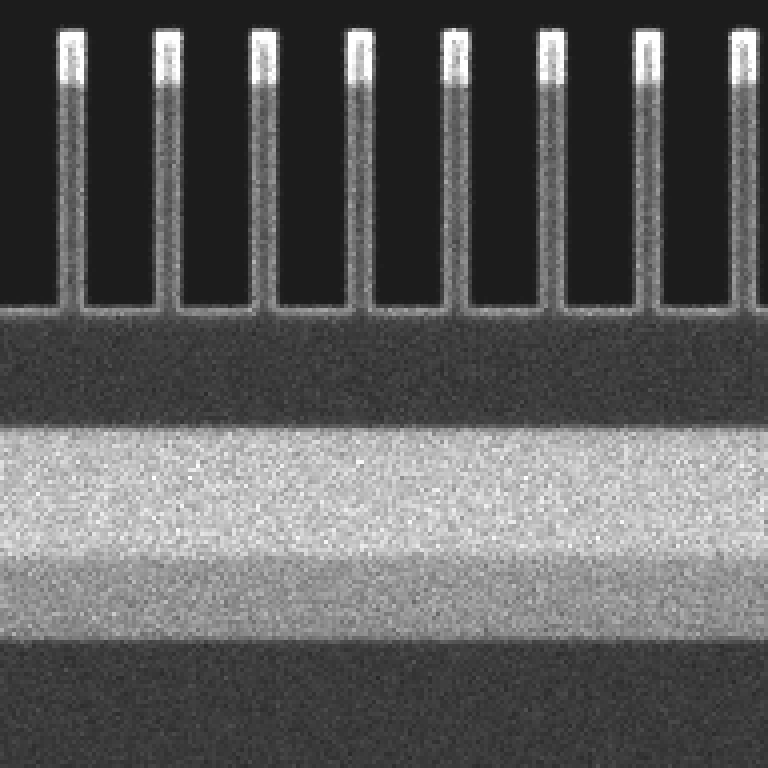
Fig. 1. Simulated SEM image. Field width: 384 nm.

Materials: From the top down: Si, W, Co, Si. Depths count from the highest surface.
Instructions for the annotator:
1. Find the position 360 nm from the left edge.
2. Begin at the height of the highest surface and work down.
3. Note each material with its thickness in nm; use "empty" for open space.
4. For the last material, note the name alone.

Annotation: empty 138, Si 60, W 64, Co 42, Si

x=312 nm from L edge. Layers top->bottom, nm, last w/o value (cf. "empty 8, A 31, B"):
empty 138, Si 60, W 64, Co 42, Si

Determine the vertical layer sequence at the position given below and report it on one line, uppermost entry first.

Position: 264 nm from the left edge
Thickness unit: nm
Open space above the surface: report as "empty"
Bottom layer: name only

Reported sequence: empty 138, Si 60, W 64, Co 42, Si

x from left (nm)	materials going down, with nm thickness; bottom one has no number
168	empty 138, Si 60, W 64, Co 42, Si